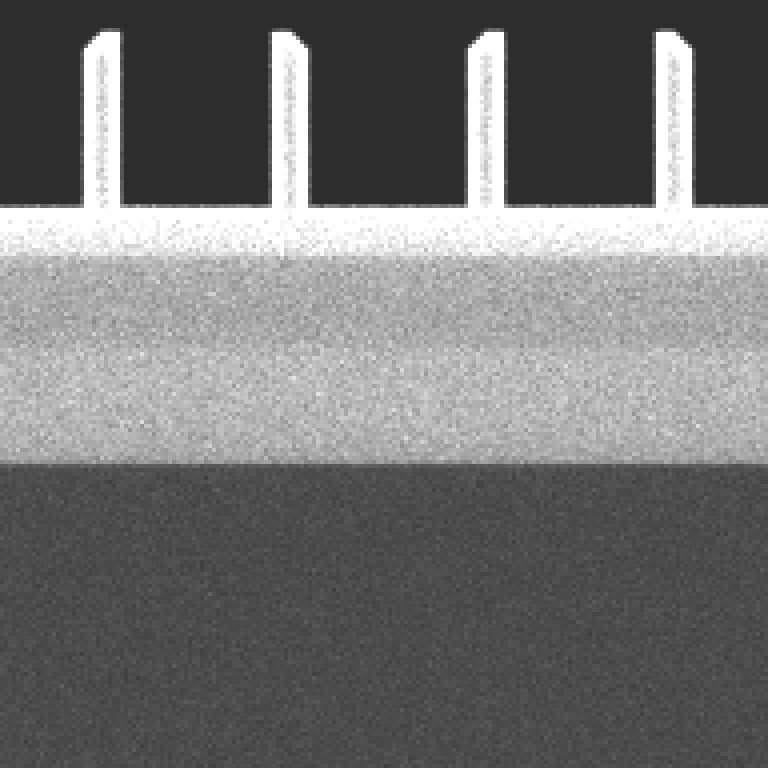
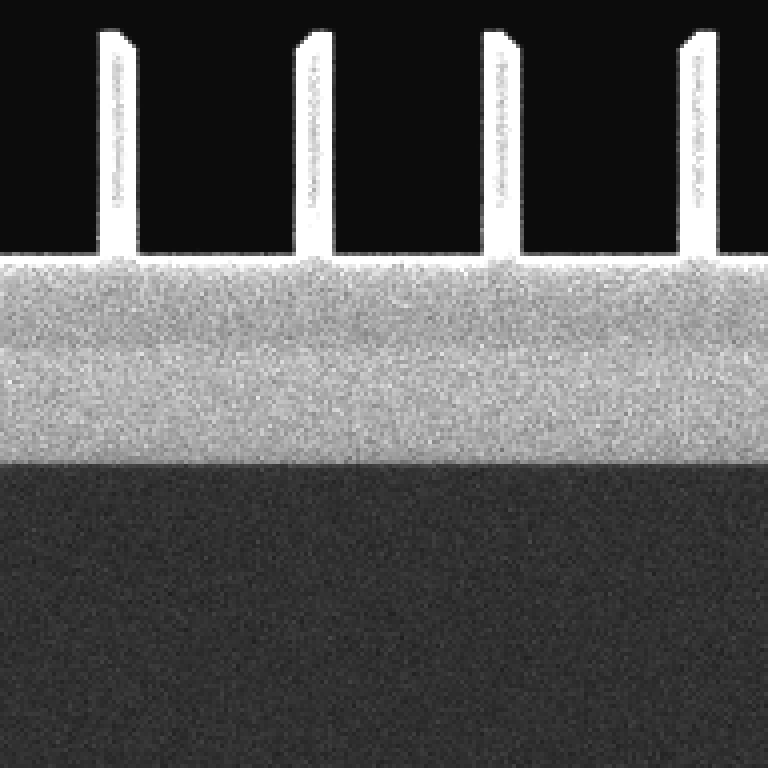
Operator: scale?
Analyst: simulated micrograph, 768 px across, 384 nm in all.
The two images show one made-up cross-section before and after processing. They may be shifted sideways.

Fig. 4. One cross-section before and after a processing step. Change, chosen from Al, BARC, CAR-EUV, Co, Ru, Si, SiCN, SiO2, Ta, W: W removed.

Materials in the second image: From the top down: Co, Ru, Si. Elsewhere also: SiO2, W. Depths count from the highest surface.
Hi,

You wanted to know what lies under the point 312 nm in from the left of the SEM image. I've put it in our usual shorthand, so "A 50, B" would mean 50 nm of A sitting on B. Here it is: empty 112, Co 46, Ru 58, Si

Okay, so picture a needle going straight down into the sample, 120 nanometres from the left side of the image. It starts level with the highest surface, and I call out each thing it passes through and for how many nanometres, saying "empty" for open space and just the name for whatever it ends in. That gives empty 112, Co 46, Ru 58, Si